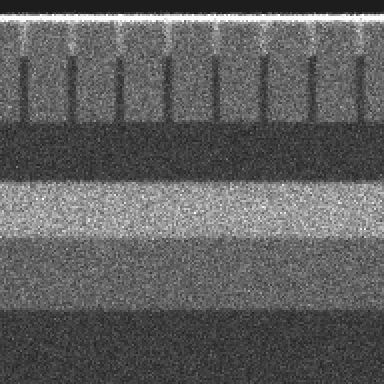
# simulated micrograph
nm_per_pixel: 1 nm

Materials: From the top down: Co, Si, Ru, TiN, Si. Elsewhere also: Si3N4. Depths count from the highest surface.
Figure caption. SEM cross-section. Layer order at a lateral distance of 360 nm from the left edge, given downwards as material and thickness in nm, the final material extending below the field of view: Co 40, Si 126, Ru 56, TiN 72, Si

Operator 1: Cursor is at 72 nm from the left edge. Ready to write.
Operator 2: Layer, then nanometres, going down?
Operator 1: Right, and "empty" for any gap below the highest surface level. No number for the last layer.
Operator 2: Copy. Co 40, Si 126, Ru 56, TiN 72, Si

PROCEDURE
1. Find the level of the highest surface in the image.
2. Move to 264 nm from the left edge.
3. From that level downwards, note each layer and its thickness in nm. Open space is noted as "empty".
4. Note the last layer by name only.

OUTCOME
Co 40, Si 126, Ru 56, TiN 72, Si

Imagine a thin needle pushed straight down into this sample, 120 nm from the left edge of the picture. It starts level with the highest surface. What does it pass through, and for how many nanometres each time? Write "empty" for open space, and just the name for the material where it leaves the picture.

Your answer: Co 40, Si 126, Ru 56, TiN 72, Si